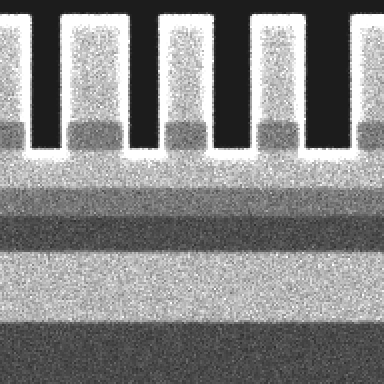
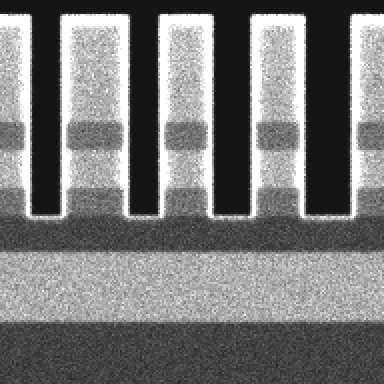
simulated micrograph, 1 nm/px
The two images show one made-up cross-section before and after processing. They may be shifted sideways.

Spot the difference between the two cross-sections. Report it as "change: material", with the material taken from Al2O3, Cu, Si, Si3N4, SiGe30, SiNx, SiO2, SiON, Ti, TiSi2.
removed: SiNx and SiO2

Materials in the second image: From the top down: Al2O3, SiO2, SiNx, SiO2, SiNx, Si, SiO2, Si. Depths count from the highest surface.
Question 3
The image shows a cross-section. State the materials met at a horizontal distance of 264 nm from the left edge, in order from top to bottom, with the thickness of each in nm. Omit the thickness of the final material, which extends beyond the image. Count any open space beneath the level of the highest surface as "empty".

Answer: Al2O3 60, SiO2 46, SiNx 28, SiO2 38, SiNx 28, Si 36, SiO2 70, Si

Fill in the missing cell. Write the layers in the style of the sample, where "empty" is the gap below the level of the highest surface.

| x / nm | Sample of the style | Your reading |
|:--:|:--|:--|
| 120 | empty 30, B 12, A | Al2O3 60, SiO2 46, SiNx 28, SiO2 38, SiNx 28, Si 36, SiO2 70, Si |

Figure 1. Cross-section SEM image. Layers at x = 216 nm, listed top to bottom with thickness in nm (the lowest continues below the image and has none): empty 200, Si 36, SiO2 70, Si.